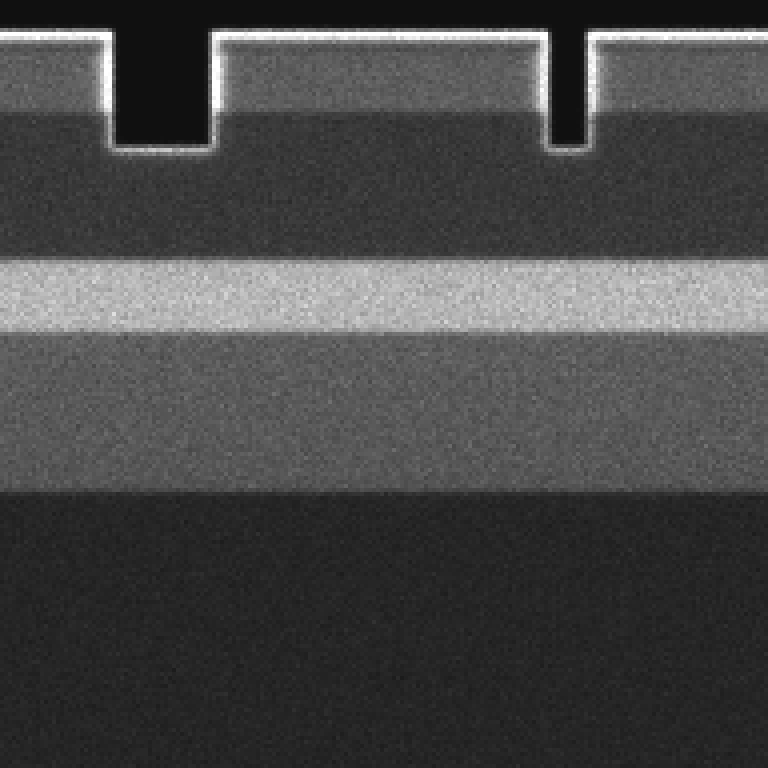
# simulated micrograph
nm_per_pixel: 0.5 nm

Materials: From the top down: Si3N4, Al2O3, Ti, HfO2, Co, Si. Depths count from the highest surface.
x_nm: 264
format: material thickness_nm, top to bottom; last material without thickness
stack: Si3N4 10, Al2O3 30, Ti 74, HfO2 36, Co 80, Si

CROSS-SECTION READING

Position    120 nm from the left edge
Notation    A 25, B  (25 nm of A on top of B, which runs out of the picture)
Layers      Si3N4 10, Al2O3 30, Ti 74, HfO2 36, Co 80, Si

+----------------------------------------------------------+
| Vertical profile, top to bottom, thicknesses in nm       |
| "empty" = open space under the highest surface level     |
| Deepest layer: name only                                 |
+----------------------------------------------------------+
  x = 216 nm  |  Si3N4 10, Al2O3 30, Ti 74, HfO2 36, Co 80, Si